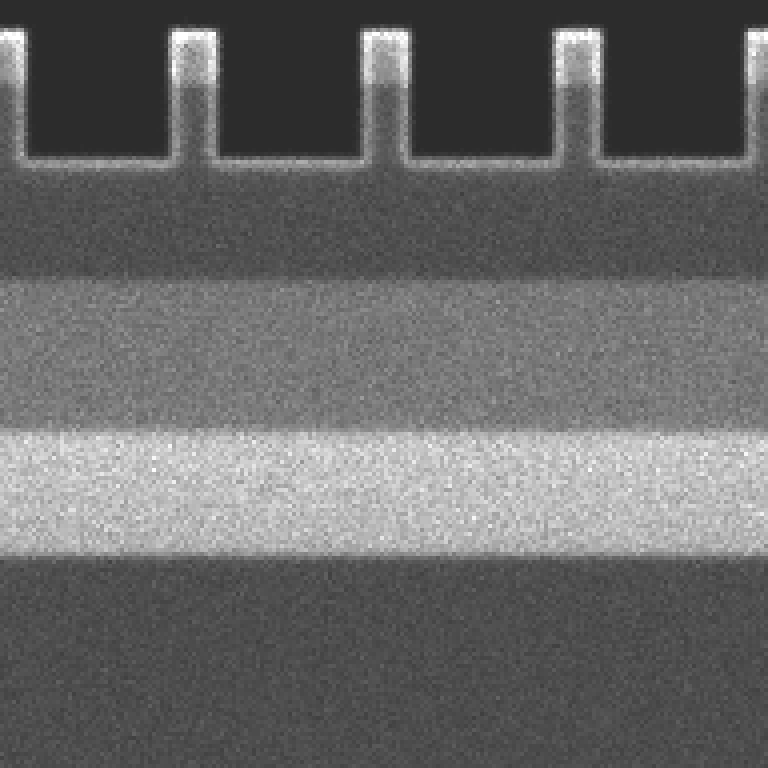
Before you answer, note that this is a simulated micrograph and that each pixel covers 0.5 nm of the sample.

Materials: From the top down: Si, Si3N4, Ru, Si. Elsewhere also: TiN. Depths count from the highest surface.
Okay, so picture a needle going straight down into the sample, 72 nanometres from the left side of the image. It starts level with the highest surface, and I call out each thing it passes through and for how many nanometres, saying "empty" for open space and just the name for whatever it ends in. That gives empty 64, Si 60, Si3N4 76, Ru 62, Si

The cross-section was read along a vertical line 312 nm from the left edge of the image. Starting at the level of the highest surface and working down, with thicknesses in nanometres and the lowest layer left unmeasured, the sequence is empty 64, Si 60, Si3N4 76, Ru 62, Si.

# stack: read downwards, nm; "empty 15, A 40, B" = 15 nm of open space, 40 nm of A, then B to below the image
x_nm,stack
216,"empty 64, Si 60, Si3N4 76, Ru 62, Si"